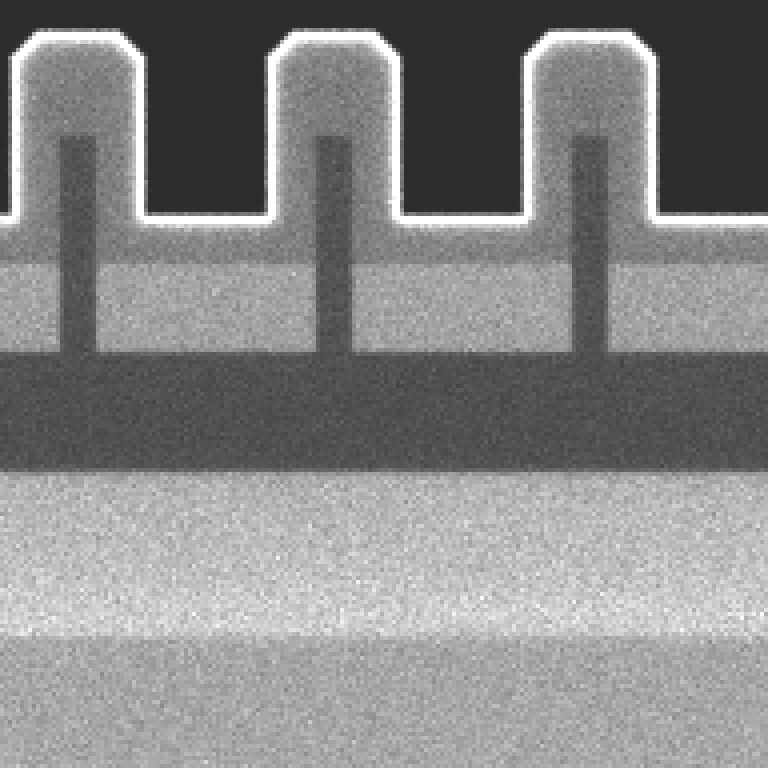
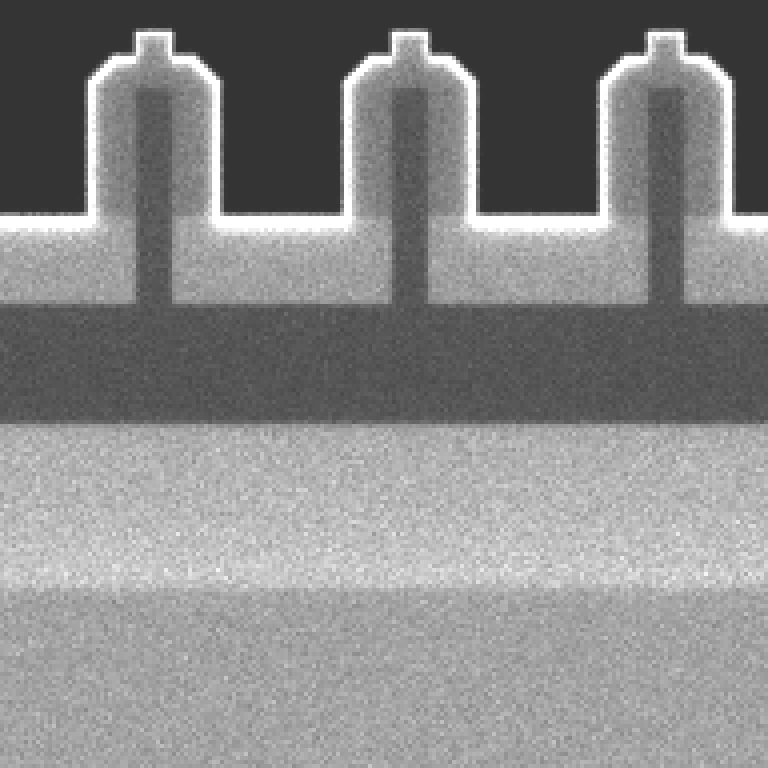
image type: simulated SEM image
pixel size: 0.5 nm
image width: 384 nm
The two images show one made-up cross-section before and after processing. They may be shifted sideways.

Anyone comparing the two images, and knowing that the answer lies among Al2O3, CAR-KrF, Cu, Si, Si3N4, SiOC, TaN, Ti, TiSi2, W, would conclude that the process removed Si3N4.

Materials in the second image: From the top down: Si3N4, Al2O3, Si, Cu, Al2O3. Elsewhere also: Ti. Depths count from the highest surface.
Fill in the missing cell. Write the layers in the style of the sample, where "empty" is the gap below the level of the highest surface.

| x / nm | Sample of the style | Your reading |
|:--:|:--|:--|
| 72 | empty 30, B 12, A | Ti 28, Si 168, Cu 82, Al2O3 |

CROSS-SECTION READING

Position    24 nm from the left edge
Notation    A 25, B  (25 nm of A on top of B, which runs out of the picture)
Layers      empty 92, Al2O3 44, Si 60, Cu 82, Al2O3